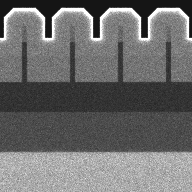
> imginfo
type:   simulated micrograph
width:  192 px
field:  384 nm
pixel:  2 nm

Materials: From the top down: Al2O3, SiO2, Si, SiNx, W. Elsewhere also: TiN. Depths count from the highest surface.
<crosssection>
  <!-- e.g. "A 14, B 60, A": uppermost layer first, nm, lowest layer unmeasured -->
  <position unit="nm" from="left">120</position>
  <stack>empty 2, Al2O3 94, SiO2 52, Si 60, SiNx 80, W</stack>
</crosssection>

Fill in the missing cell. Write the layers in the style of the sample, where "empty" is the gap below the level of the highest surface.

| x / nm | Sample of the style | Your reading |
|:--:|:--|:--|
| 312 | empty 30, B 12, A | empty 2, Al2O3 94, SiO2 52, Si 60, SiNx 80, W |